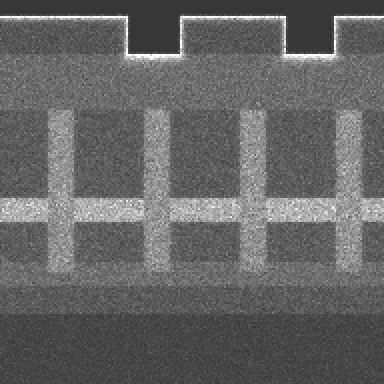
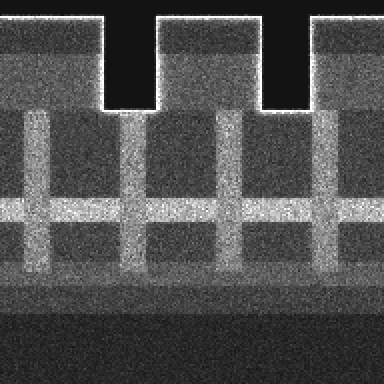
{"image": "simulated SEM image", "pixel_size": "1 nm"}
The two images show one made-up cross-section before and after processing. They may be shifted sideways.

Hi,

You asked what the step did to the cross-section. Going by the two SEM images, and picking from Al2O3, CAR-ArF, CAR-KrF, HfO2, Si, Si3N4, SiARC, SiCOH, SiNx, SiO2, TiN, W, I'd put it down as SiO2, removed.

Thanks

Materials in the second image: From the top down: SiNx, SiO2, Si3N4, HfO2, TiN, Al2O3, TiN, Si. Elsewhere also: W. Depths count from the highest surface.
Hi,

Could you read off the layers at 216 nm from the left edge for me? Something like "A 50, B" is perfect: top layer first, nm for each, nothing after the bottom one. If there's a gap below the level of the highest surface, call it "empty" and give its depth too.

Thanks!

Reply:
SiNx 38, SiO2 56, W 162, Al2O3 14, TiN 28, Si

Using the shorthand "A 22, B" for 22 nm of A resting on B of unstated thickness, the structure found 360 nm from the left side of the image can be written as SiNx 38, SiO2 56, Si3N4 88, HfO2 24, TiN 40, Al2O3 24, TiN 28, Si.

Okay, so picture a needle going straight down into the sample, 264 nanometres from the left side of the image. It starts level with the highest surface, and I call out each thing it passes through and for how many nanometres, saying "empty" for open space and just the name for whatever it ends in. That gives empty 94, Si3N4 88, HfO2 24, TiN 40, Al2O3 24, TiN 28, Si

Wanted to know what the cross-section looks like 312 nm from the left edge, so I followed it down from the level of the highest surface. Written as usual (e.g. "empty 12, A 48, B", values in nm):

SiNx 38, SiO2 56, W 162, Al2O3 14, TiN 28, Si